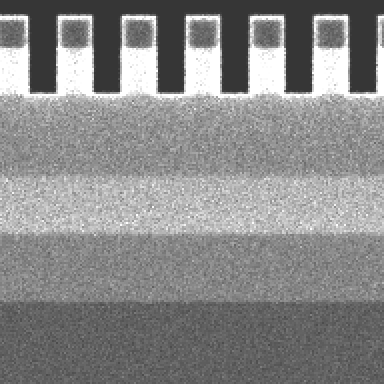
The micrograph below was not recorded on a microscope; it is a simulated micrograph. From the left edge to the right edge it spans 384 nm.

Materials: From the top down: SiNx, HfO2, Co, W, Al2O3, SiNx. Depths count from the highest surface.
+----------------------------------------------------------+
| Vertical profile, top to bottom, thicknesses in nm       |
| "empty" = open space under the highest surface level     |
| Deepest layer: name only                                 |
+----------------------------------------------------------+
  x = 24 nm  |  SiNx 32, HfO2 46, Co 82, W 58, Al2O3 68, SiNx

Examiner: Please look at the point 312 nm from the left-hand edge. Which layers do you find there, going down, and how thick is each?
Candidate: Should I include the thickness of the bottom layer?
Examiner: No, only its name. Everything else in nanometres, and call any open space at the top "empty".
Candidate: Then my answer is empty 78, Co 82, W 58, Al2O3 68, SiNx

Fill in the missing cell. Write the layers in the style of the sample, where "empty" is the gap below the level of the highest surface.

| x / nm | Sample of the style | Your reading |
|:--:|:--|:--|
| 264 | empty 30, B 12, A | SiNx 32, HfO2 46, Co 82, W 58, Al2O3 68, SiNx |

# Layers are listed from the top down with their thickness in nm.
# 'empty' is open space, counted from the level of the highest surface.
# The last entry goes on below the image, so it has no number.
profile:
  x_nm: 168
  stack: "empty 78, Co 82, W 58, Al2O3 68, SiNx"